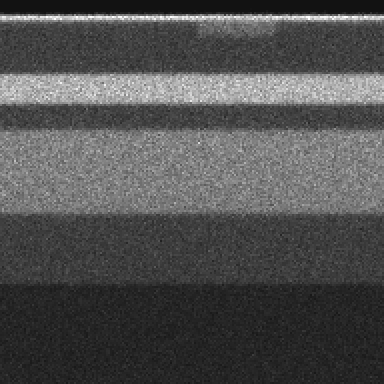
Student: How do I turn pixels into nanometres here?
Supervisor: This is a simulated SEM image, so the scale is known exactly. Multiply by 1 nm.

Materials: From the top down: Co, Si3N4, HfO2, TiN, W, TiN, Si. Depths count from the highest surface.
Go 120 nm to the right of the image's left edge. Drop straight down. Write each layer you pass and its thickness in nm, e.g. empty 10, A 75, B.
Si3N4 58, HfO2 30, TiN 26, W 84, TiN 70, Si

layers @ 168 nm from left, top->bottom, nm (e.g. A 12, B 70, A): Si3N4 58, HfO2 30, TiN 26, W 84, TiN 70, Si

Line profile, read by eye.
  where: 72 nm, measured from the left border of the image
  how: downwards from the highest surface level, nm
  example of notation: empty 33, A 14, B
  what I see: Si3N4 58, HfO2 30, TiN 26, W 84, TiN 70, Si